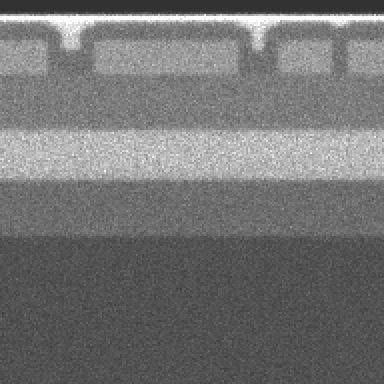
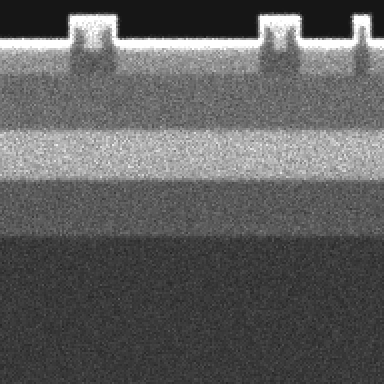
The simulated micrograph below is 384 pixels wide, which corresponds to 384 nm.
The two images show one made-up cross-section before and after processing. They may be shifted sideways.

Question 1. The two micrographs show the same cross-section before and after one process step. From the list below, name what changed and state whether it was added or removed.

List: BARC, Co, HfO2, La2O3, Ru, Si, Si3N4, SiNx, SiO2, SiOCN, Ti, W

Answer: SiNx, removed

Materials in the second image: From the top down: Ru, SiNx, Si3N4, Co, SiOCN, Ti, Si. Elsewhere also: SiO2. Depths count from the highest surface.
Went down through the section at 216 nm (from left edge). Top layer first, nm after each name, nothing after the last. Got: empty 24, SiO2 34, Si3N4 56, Co 50, SiOCN 48, Ti 8, Si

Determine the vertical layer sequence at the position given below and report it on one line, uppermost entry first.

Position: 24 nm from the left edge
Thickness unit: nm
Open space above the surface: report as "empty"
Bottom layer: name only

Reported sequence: empty 24, SiO2 34, Si3N4 56, Co 50, SiOCN 48, Ti 8, Si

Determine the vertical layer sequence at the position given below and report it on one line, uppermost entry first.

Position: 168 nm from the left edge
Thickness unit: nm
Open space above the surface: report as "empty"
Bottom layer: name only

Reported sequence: empty 24, SiO2 34, Si3N4 56, Co 50, SiOCN 48, Ti 8, Si